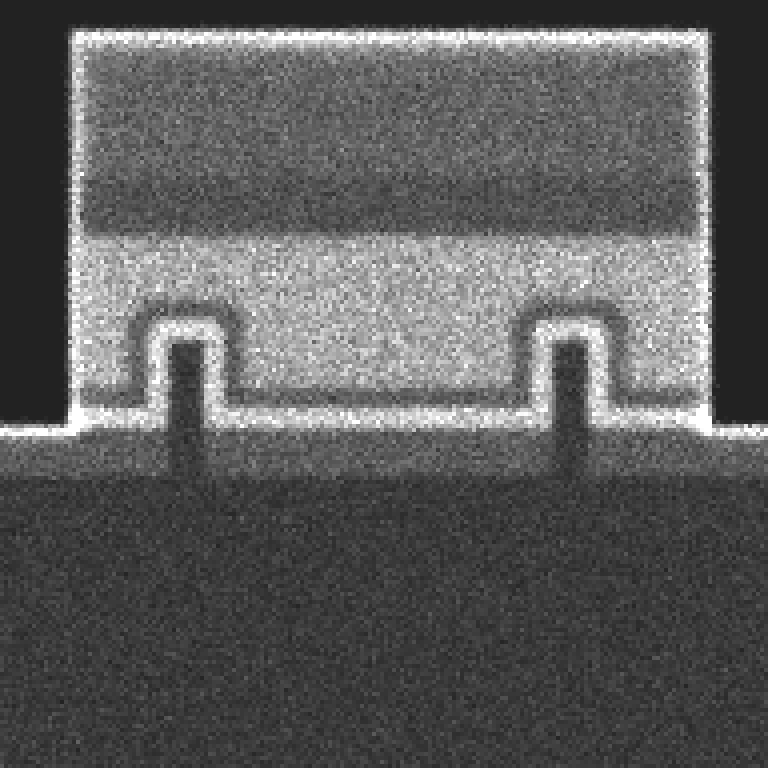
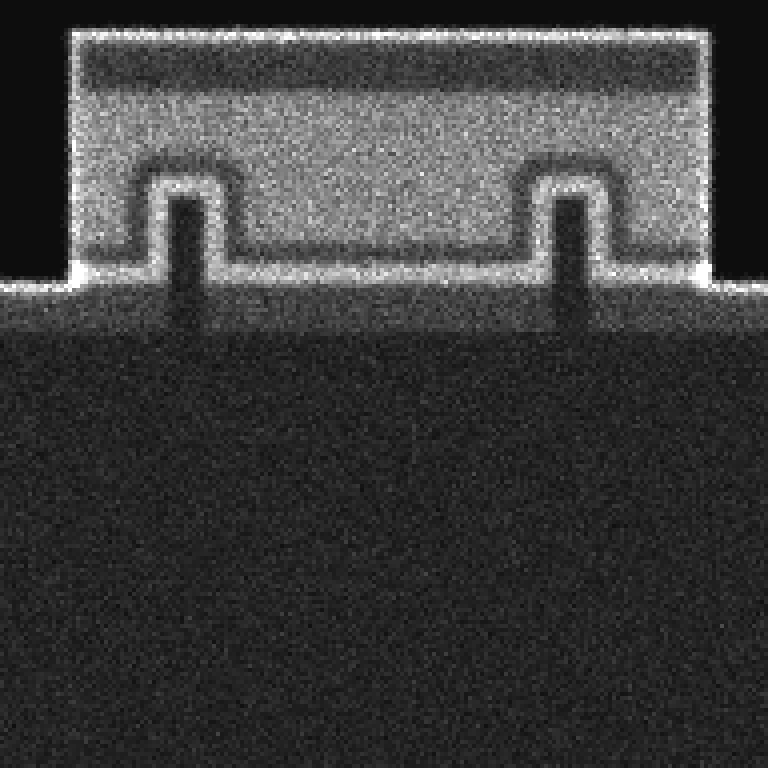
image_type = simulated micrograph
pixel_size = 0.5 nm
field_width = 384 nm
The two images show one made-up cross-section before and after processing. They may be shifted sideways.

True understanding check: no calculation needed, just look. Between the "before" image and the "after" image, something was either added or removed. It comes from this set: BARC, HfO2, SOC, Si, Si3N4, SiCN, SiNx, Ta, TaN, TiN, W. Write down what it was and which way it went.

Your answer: SOC (removed)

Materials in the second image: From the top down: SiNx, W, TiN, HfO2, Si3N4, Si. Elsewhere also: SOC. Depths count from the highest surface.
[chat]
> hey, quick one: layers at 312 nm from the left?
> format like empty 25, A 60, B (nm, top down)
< SiNx 30, W 40, TiN 46, HfO2 10, Si3N4 24, Si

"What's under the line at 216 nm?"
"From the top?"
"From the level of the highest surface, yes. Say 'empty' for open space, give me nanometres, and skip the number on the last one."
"SiNx 30, W 76, TiN 10, HfO2 10, Si3N4 24, Si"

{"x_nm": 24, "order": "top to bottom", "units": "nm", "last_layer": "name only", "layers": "empty 126, Si3N4 24, Si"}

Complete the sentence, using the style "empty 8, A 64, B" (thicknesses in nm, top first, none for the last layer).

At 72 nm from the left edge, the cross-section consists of SiNx 30, W 32, TiN 54, HfO2 10, Si3N4 24, Si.